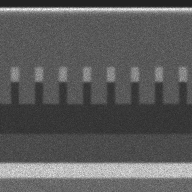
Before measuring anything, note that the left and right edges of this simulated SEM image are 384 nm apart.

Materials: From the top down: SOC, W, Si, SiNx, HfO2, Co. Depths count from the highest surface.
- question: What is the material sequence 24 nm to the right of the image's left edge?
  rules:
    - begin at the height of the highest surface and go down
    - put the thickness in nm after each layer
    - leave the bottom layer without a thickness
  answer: SOC 118, W 30, Si 104, SiNx 58, HfO2 30, Co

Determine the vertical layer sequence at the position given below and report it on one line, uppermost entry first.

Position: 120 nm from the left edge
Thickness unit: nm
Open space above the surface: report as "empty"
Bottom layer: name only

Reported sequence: SOC 118, W 30, Si 104, SiNx 58, HfO2 30, Co